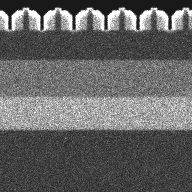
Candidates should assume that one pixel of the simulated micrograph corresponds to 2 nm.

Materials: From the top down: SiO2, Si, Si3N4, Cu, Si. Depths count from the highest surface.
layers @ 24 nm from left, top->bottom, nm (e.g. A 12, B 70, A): empty 16, SiO2 28, Si 60, Si3N4 74, Cu 66, Si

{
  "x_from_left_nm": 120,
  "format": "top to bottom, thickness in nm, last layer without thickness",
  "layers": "Si 104, Si3N4 74, Cu 66, Si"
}